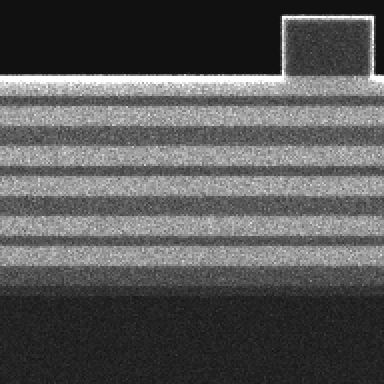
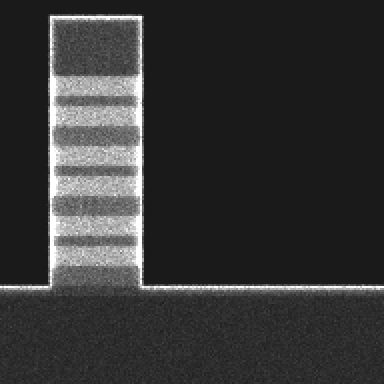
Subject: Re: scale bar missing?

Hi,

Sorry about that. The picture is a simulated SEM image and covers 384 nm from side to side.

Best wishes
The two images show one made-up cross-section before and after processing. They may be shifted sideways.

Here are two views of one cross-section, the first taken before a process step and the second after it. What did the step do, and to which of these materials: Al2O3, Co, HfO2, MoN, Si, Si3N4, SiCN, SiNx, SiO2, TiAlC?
It removed Al2O3 and Co and HfO2.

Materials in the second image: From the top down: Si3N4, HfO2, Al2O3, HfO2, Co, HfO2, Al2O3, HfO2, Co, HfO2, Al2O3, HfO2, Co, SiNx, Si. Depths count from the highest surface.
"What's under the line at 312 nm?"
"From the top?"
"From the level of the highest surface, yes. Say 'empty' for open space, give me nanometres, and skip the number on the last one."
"empty 270, SiNx 10, Si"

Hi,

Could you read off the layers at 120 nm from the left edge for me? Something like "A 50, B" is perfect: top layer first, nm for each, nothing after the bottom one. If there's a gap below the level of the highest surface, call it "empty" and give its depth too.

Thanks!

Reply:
Si3N4 60, HfO2 20, Al2O3 10, HfO2 20, Co 20, HfO2 20, Al2O3 10, HfO2 20, Co 20, HfO2 20, Al2O3 10, HfO2 20, Co 20, SiNx 10, Si